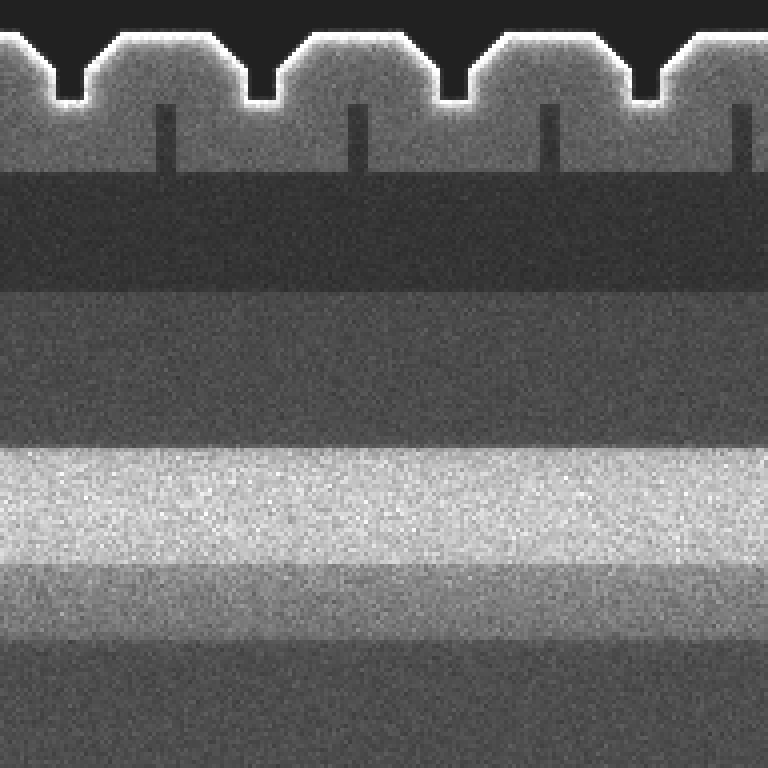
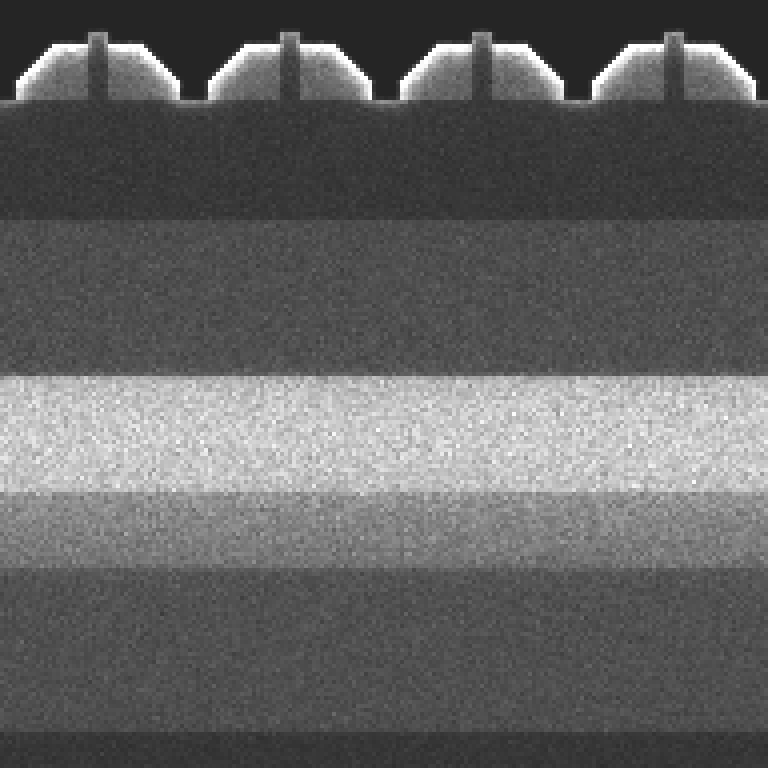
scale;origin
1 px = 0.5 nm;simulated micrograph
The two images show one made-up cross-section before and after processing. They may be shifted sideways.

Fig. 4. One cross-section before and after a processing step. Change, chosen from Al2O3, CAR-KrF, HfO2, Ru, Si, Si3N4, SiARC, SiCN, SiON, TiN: Al2O3 removed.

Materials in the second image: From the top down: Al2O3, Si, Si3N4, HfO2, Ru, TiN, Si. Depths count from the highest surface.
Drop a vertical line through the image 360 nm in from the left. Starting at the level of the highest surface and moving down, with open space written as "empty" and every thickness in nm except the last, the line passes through empty 8, Al2O3 26, Si 60, Si3N4 78, HfO2 58, Ru 38, TiN 82, Si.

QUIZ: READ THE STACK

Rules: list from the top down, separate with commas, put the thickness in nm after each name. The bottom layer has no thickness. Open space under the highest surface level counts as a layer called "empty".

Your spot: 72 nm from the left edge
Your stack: empty 8, Al2O3 26, Si 60, Si3N4 78, HfO2 58, Ru 38, TiN 82, Si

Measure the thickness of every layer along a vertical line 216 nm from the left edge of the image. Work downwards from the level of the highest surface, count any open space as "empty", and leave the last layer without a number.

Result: empty 8, Al2O3 26, Si 60, Si3N4 78, HfO2 58, Ru 38, TiN 82, Si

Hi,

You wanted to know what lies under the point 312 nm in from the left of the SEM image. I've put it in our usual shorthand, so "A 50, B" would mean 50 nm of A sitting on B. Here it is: empty 8, Al2O3 26, Si 60, Si3N4 78, HfO2 58, Ru 38, TiN 82, Si